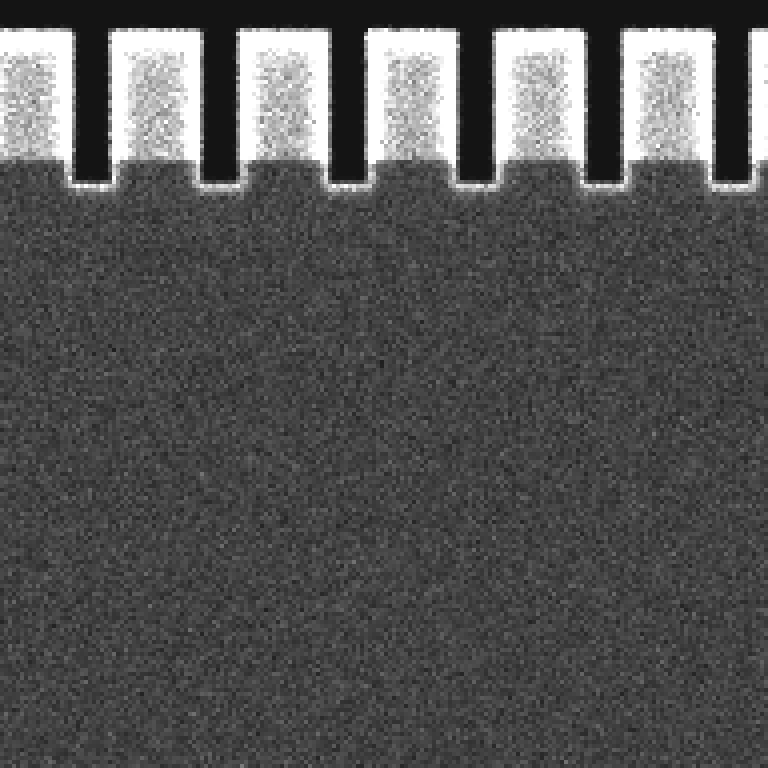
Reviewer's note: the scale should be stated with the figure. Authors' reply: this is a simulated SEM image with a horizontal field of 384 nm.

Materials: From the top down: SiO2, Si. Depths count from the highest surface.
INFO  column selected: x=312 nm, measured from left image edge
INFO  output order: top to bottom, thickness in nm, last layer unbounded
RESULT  SiO2 64, Si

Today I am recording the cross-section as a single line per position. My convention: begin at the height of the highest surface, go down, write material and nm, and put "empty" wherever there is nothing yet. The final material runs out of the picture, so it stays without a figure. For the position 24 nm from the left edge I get SiO2 64, Si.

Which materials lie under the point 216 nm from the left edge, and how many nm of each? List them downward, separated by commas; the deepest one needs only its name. SiO2 64, Si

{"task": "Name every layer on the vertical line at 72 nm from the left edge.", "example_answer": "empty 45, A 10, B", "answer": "SiO2 64, Si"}